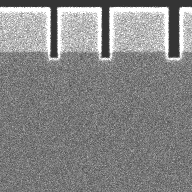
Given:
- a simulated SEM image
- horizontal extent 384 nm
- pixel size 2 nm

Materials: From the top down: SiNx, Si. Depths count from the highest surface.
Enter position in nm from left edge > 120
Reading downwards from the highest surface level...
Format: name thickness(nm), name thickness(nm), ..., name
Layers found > SiNx 88, Si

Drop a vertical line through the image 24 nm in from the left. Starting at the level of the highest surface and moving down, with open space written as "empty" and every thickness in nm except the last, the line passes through SiNx 88, Si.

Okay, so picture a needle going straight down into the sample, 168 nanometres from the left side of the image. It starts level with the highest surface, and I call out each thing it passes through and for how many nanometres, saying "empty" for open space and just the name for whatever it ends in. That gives SiNx 88, Si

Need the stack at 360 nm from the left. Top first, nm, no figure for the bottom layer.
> SiNx 88, Si